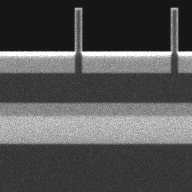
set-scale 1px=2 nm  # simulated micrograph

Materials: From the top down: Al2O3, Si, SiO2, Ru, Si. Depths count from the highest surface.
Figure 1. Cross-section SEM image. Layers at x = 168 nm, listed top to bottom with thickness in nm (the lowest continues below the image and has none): empty 88, Al2O3 42, Si 60, SiO2 26, Ru 56, Si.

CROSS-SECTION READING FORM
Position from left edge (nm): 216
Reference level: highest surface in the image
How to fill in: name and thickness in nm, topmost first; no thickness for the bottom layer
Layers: empty 88, Al2O3 42, Si 60, SiO2 26, Ru 56, Si